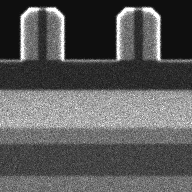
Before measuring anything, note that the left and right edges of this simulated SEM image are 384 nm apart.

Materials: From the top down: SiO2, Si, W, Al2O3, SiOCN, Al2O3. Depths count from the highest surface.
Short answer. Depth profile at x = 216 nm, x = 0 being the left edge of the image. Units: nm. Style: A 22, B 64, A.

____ empty 104, Si 60, W 76, Al2O3 32, SiOCN 64, Al2O3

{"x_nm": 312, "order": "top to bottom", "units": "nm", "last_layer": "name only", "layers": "empty 10, SiO2 94, Si 60, W 76, Al2O3 32, SiOCN 64, Al2O3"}